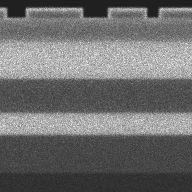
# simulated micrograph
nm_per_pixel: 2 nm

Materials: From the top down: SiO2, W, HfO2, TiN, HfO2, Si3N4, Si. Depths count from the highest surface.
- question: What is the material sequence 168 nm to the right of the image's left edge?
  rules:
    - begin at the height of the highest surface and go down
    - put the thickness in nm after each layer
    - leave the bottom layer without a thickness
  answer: empty 20, W 48, HfO2 74, TiN 68, HfO2 44, Si3N4 76, Si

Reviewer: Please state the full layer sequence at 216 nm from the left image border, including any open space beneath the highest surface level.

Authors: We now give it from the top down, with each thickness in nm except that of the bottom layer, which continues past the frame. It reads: SiO2 20, W 48, HfO2 74, TiN 68, HfO2 44, Si3N4 76, Si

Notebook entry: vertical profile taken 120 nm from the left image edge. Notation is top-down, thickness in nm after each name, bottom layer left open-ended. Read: SiO2 20, W 48, HfO2 74, TiN 68, HfO2 44, Si3N4 76, Si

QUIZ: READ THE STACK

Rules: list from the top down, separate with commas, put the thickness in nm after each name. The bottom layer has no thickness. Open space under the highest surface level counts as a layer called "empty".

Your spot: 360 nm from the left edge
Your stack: SiO2 20, W 48, HfO2 74, TiN 68, HfO2 44, Si3N4 76, Si